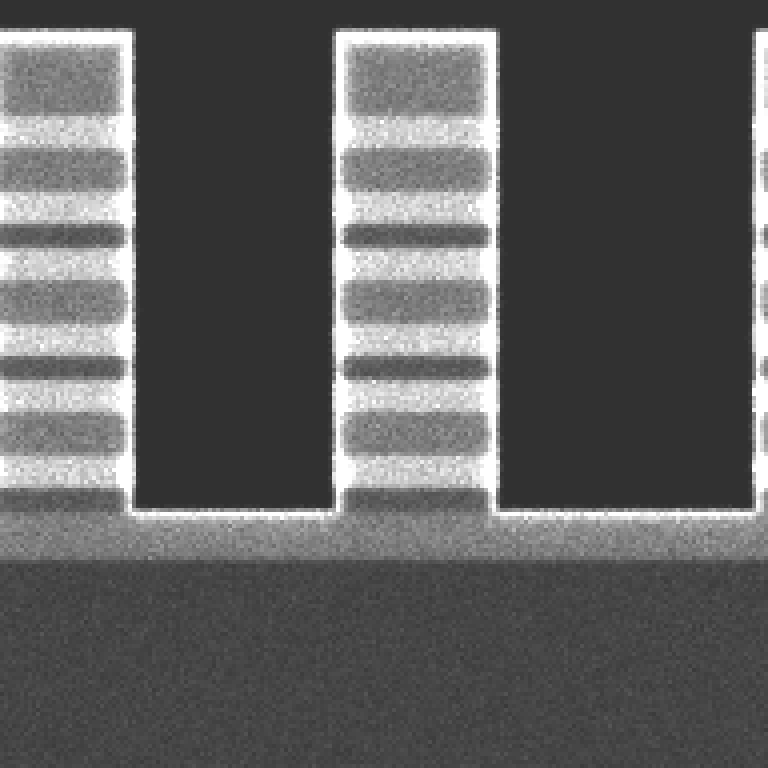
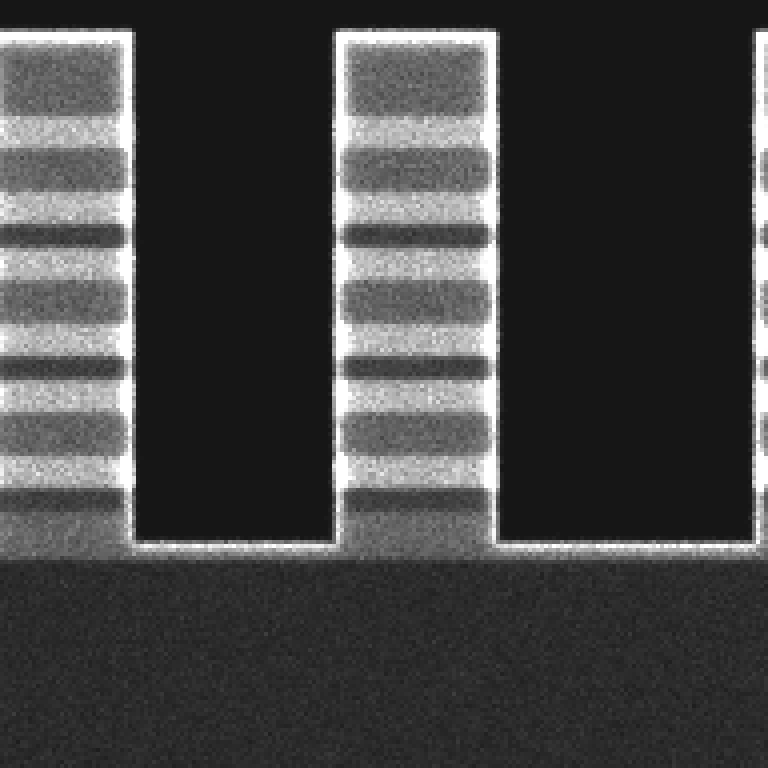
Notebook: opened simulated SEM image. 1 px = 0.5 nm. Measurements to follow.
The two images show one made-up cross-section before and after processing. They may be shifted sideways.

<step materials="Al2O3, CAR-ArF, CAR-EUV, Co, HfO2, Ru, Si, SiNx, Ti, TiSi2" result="removed Ru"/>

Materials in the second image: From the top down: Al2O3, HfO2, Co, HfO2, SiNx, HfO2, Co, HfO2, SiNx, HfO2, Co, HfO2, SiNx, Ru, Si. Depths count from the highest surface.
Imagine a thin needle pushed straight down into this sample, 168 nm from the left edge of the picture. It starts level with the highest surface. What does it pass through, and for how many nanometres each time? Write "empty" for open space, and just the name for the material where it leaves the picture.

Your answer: Al2O3 42, HfO2 16, Co 22, HfO2 16, SiNx 12, HfO2 16, Co 22, HfO2 16, SiNx 12, HfO2 16, Co 22, HfO2 16, SiNx 12, Ru 24, Si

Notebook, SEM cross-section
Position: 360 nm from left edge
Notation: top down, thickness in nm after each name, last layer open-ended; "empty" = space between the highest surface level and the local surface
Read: empty 256, Ru 8, Si